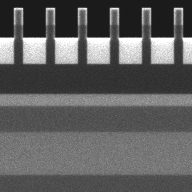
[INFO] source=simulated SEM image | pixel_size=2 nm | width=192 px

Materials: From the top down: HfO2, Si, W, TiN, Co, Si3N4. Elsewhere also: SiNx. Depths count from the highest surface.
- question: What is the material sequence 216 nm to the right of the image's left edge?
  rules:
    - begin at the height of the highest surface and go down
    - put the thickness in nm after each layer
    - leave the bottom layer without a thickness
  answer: empty 60, HfO2 52, Si 60, W 24, TiN 52, Co 86, Si3N4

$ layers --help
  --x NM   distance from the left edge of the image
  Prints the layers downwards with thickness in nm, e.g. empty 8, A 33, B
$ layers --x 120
empty 60, HfO2 52, Si 60, W 24, TiN 52, Co 86, Si3N4